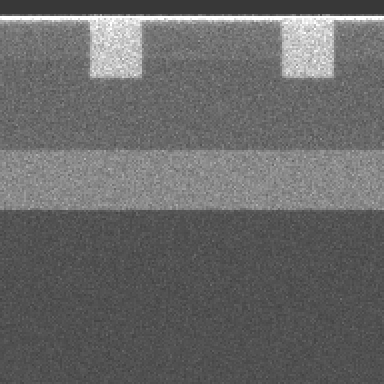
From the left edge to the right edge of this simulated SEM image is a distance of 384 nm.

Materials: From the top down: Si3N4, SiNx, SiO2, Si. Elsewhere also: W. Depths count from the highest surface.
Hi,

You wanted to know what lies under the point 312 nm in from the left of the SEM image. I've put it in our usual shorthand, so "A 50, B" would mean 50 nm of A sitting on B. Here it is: W 62, SiNx 72, SiO2 60, Si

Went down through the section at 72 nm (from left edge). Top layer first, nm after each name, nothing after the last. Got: Si3N4 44, SiNx 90, SiO2 60, Si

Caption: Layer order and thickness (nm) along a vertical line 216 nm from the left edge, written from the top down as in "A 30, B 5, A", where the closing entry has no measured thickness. Si3N4 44, SiNx 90, SiO2 60, Si